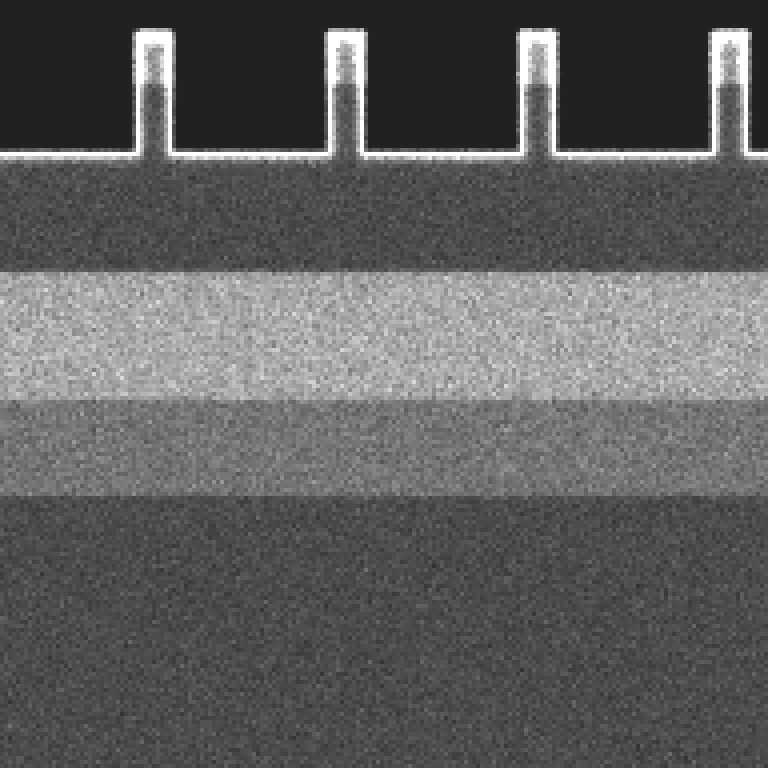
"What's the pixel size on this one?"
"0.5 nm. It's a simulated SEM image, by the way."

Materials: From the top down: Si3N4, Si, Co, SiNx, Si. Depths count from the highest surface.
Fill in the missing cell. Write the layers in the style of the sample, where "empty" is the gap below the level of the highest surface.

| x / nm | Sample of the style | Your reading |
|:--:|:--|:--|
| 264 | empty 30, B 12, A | Si3N4 26, Si 94, Co 64, SiNx 48, Si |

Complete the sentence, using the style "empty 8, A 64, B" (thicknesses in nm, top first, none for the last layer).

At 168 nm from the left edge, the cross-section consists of Si3N4 26, Si 94, Co 64, SiNx 48, Si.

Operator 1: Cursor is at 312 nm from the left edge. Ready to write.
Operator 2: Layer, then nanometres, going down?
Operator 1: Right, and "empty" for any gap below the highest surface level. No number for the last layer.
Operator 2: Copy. empty 60, Si 60, Co 64, SiNx 48, Si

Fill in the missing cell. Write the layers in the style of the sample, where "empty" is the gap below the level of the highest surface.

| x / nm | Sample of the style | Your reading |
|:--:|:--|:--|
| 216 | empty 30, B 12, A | empty 60, Si 60, Co 64, SiNx 48, Si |